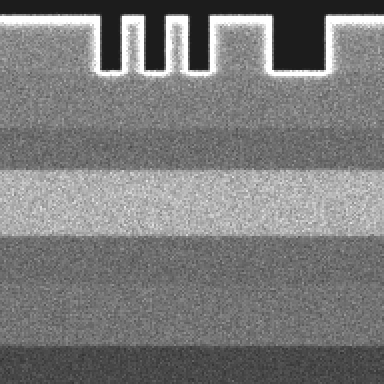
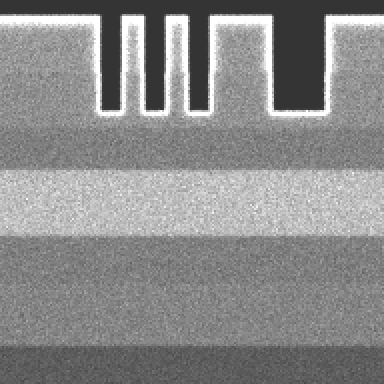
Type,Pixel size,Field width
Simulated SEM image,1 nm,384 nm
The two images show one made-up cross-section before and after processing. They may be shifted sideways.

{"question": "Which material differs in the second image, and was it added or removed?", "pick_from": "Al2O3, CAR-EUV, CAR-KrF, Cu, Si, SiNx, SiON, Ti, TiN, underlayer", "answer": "TiN, removed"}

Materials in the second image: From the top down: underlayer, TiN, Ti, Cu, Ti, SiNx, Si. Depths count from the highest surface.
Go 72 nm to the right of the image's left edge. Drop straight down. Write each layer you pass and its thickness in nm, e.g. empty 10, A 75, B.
underlayer 56, TiN 56, Ti 42, Cu 66, Ti 48, SiNx 62, Si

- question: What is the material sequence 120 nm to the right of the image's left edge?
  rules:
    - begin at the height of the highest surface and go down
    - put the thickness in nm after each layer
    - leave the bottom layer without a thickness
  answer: empty 96, TiN 16, Ti 42, Cu 66, Ti 48, SiNx 62, Si